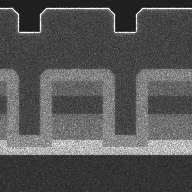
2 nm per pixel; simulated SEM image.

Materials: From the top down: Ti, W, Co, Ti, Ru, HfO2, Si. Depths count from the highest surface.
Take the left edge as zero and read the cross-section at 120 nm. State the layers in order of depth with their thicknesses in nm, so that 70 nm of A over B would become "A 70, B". Ti 122, W 24, Co 30, Ti 36, Ru 52, HfO2 30, Si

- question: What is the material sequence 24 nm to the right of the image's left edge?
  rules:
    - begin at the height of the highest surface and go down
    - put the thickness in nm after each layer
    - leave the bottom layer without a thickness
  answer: Ti 122, W 156, HfO2 16, Si